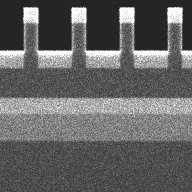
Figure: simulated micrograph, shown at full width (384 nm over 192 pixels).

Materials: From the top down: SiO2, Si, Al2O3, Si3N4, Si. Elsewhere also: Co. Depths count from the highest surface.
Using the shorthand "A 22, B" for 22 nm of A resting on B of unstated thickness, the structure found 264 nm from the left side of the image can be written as Co 30, Si 150, Al2O3 32, Si3N4 54, Si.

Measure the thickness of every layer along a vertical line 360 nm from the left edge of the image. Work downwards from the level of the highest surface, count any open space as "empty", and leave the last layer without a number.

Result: Co 30, Si 150, Al2O3 32, Si3N4 54, Si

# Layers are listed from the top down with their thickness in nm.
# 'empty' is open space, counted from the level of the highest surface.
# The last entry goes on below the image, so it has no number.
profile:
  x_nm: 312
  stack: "empty 86, SiO2 34, Si 60, Al2O3 32, Si3N4 54, Si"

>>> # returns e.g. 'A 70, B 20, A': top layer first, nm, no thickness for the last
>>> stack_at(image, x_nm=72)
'Co 30, Si 150, Al2O3 32, Si3N4 54, Si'